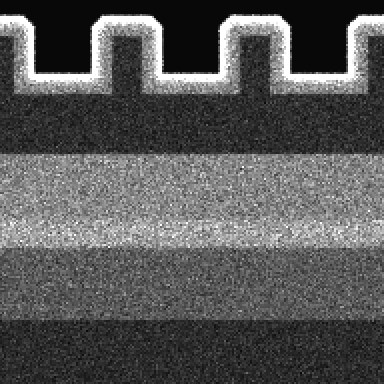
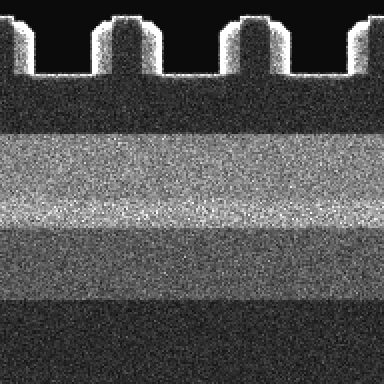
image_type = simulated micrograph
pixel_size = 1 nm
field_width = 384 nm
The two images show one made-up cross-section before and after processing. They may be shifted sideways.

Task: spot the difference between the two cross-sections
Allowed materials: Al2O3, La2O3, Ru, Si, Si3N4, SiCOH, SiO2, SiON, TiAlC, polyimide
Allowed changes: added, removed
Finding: removed SiO2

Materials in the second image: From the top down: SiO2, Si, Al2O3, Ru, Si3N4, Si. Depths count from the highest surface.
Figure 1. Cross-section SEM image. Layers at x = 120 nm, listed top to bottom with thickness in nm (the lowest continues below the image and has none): Si 118, Al2O3 66, Ru 28, Si3N4 72, Si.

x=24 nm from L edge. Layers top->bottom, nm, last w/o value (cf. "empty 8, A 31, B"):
empty 8, SiO2 50, Si 60, Al2O3 66, Ru 28, Si3N4 72, Si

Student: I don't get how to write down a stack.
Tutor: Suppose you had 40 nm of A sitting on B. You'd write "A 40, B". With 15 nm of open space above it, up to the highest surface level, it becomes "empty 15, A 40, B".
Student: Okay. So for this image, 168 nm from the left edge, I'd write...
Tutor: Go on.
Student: empty 58, Si 60, Al2O3 66, Ru 28, Si3N4 72, Si